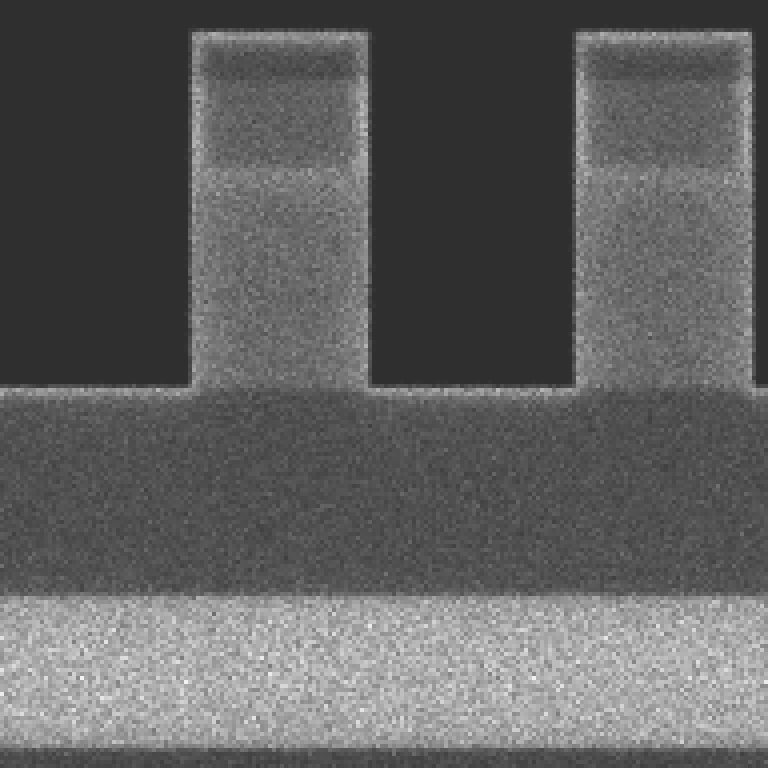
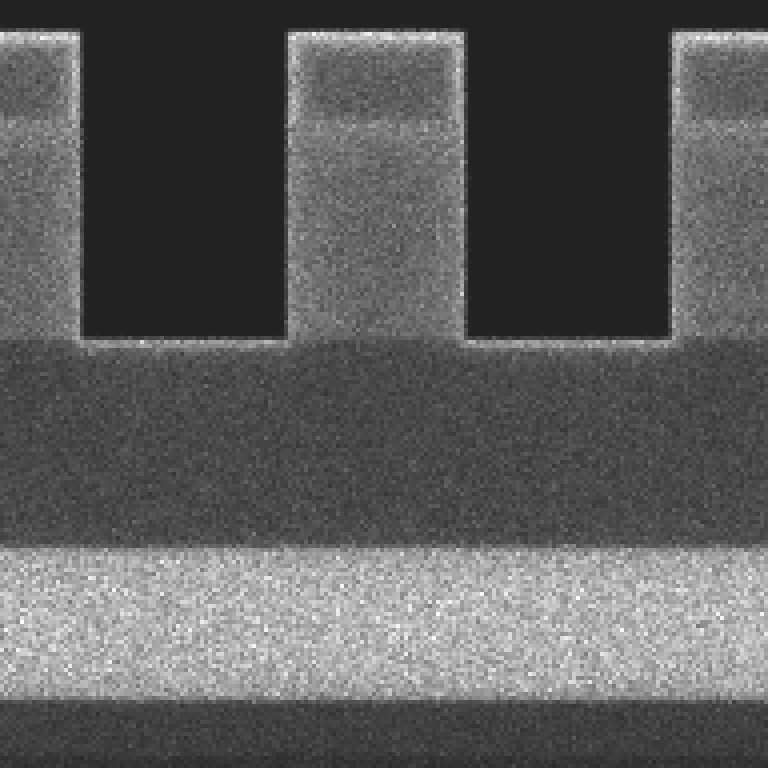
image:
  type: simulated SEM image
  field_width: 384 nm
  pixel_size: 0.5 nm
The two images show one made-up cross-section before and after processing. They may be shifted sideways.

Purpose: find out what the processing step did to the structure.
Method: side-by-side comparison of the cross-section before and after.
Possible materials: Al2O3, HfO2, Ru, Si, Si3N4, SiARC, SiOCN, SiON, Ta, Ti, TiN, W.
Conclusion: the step removed SiARC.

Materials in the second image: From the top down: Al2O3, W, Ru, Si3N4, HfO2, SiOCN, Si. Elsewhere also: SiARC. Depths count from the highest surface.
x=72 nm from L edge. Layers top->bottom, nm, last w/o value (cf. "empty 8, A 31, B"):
empty 154, Si3N4 104, HfO2 76, SiOCN 28, Si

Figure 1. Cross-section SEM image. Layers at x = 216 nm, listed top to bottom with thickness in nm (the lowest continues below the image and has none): Al2O3 44, W 94, Ru 16, Si3N4 104, HfO2 76, SiOCN 28, Si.